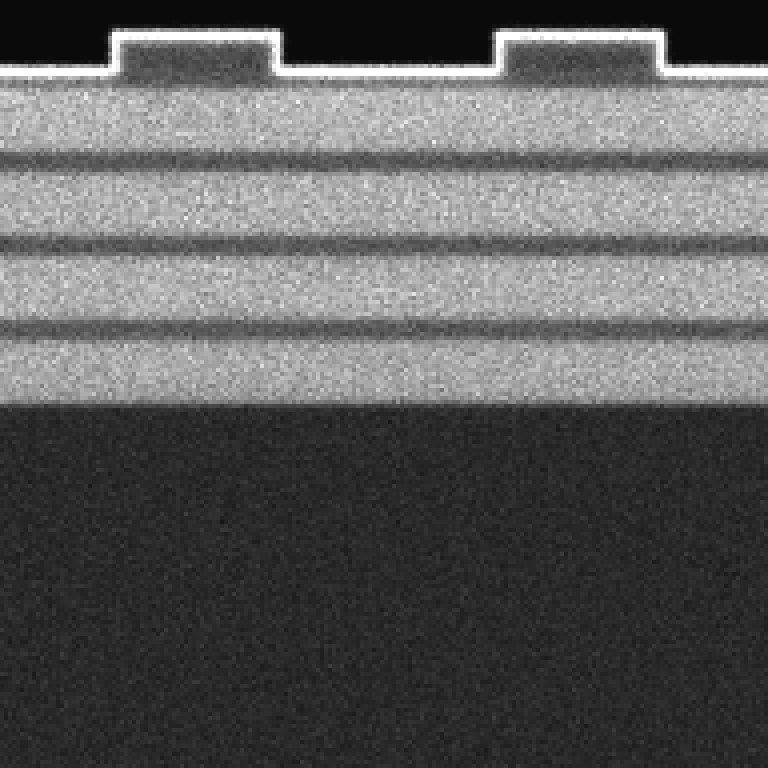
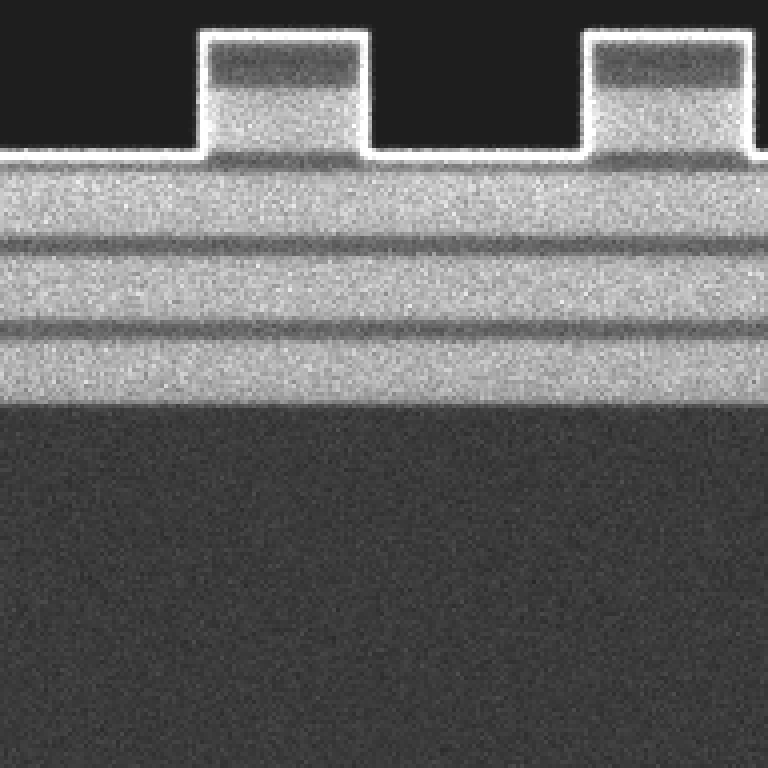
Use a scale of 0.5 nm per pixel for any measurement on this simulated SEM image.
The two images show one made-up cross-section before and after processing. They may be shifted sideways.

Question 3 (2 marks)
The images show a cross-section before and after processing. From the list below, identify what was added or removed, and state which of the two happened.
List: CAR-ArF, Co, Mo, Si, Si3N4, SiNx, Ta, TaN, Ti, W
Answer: Si3N4 and W was removed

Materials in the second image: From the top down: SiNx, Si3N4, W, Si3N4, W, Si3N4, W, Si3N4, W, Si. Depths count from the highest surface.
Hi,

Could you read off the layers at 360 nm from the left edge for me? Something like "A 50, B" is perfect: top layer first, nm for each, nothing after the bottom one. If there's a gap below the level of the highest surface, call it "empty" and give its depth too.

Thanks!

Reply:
SiNx 18, Si3N4 10, W 32, Si3N4 10, W 32, Si3N4 10, W 32, Si3N4 10, W 32, Si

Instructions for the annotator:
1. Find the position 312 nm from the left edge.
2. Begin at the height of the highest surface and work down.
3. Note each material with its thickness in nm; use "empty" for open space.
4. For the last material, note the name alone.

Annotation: SiNx 18, Si3N4 10, W 32, Si3N4 10, W 32, Si3N4 10, W 32, Si3N4 10, W 32, Si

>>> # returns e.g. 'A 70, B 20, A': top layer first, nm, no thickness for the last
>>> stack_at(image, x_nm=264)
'empty 60, Si3N4 10, W 32, Si3N4 10, W 32, Si3N4 10, W 32, Si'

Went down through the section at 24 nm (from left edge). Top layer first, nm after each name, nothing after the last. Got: empty 60, Si3N4 10, W 32, Si3N4 10, W 32, Si3N4 10, W 32, Si